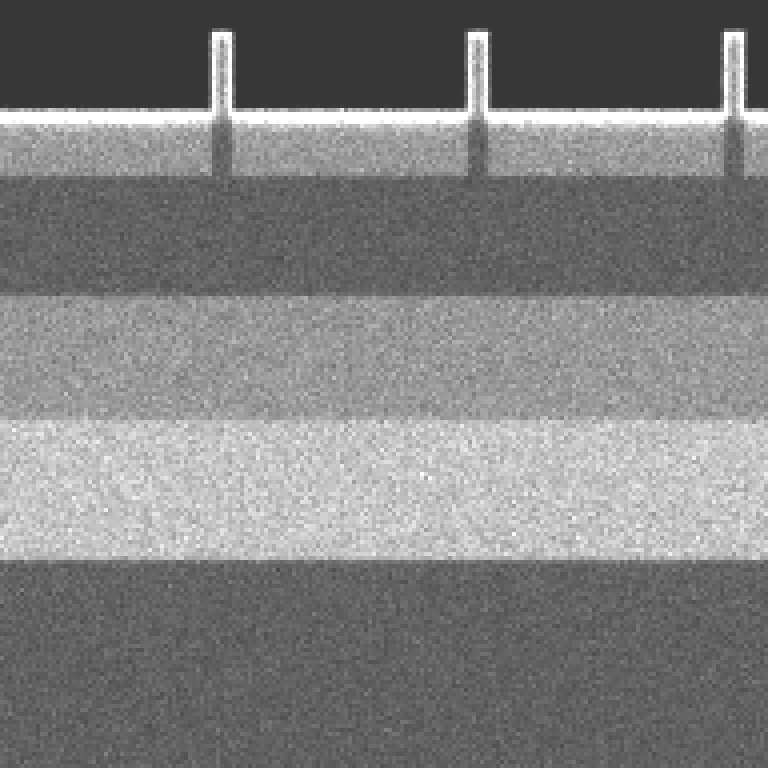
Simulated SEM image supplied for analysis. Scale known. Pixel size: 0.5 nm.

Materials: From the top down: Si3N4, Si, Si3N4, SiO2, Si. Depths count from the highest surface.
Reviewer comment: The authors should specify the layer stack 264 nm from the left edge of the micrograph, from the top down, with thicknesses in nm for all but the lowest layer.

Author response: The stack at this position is empty 40, Si3N4 32, Si 60, Si3N4 62, SiO2 70, Si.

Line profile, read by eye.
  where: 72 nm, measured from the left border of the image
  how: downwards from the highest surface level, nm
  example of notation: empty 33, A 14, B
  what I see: empty 40, Si3N4 32, Si 60, Si3N4 62, SiO2 70, Si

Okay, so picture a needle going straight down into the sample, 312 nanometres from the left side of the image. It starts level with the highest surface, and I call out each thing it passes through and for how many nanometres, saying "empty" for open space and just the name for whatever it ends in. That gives empty 40, Si3N4 32, Si 60, Si3N4 62, SiO2 70, Si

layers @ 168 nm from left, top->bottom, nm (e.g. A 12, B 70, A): empty 40, Si3N4 32, Si 60, Si3N4 62, SiO2 70, Si